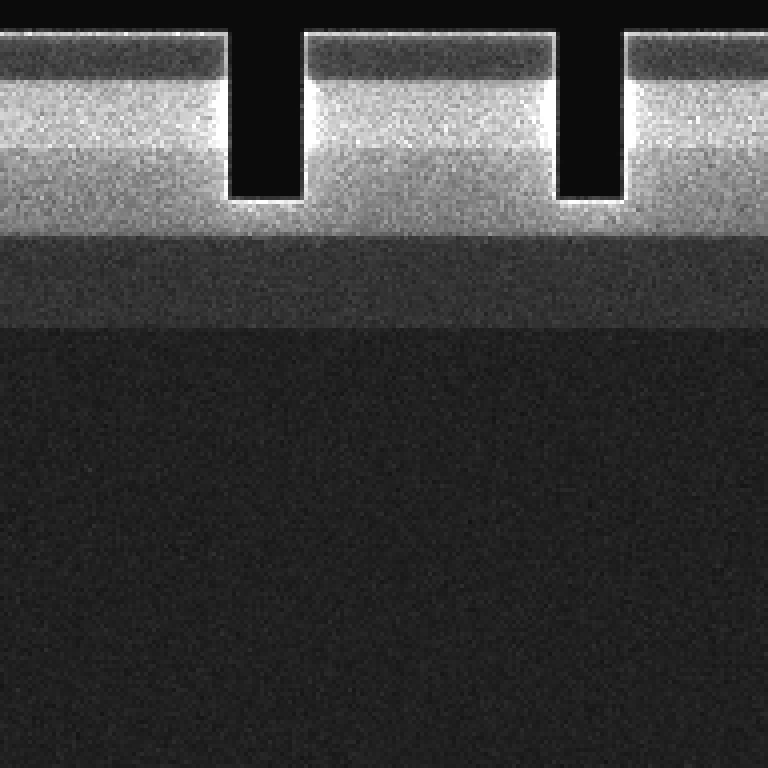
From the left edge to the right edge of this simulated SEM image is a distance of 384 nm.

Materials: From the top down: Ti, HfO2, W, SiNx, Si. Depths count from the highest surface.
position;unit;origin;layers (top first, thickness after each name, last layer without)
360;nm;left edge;Ti 24, HfO2 34, W 44, SiNx 46, Si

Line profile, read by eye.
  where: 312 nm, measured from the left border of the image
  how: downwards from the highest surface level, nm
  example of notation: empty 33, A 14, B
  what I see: Ti 24, HfO2 34, W 44, SiNx 46, Si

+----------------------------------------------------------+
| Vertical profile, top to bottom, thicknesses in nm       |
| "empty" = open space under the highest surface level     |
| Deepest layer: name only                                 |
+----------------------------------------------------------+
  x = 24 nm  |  Ti 24, HfO2 34, W 44, SiNx 46, Si